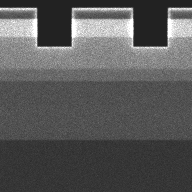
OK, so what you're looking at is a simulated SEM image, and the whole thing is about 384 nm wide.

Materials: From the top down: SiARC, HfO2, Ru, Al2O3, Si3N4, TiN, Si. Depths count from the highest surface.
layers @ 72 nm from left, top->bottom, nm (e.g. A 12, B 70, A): SiARC 22, HfO2 36, Ru 64, Al2O3 24, Si3N4 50, TiN 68, Si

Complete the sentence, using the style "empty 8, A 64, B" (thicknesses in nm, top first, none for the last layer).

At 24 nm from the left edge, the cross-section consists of SiARC 22, HfO2 36, Ru 64, Al2O3 24, Si3N4 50, TiN 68, Si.